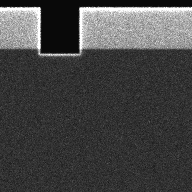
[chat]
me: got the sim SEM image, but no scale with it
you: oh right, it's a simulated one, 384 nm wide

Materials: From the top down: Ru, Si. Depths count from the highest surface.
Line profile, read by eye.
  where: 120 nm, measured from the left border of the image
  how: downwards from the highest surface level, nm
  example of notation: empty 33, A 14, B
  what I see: empty 92, Si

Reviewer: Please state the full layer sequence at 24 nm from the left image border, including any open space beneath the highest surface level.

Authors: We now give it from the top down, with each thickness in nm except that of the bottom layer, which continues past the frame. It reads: Ru 82, Si